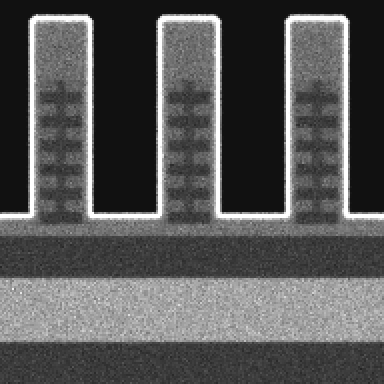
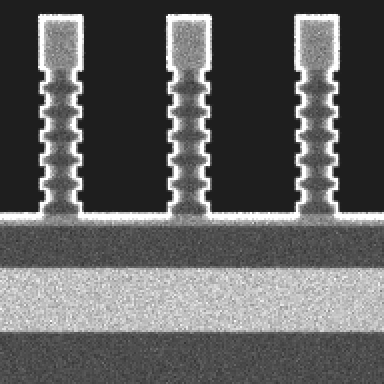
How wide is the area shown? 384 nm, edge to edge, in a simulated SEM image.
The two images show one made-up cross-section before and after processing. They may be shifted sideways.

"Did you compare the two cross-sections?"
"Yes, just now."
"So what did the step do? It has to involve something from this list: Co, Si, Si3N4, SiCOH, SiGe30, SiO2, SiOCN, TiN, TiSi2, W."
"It removed SiOCN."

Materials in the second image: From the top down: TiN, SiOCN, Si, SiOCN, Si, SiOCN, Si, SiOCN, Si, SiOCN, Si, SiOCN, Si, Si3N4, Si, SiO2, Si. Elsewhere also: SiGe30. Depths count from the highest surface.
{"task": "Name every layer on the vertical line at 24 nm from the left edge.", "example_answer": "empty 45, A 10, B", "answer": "empty 198, Si3N4 12, Si 42, SiO2 64, Si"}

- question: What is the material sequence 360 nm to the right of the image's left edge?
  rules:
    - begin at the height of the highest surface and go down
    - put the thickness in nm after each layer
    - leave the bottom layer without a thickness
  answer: empty 198, Si3N4 12, Si 42, SiO2 64, Si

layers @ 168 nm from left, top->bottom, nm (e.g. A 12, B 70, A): TiN 54, empty 12, Si 12, empty 12, Si 12, empty 12, Si 12, empty 12, Si 12, empty 12, Si 12, empty 12, Si 12, Si3N4 12, Si 42, SiO2 64, Si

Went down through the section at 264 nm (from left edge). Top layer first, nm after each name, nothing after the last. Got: empty 198, Si3N4 12, Si 42, SiO2 64, Si